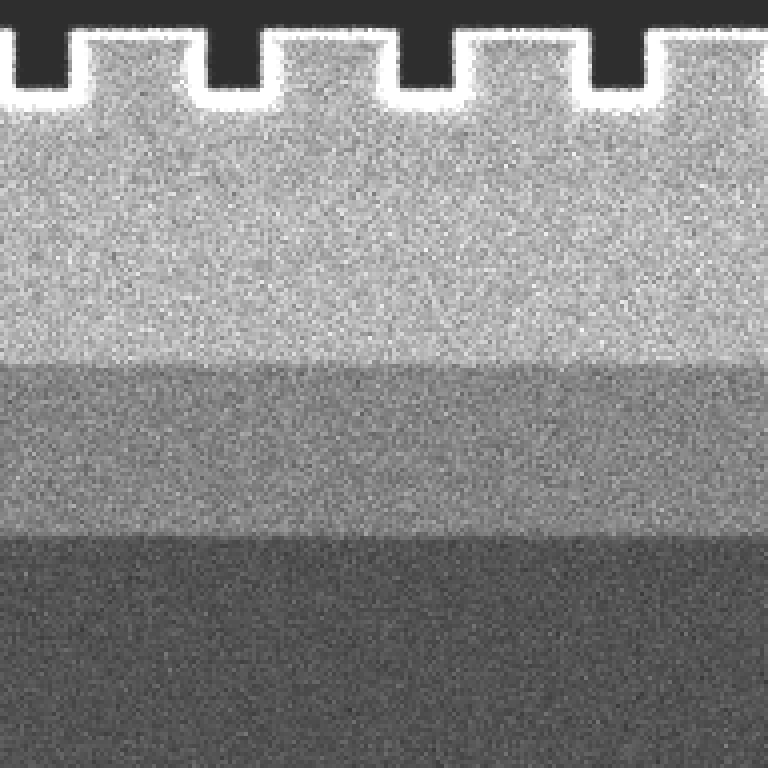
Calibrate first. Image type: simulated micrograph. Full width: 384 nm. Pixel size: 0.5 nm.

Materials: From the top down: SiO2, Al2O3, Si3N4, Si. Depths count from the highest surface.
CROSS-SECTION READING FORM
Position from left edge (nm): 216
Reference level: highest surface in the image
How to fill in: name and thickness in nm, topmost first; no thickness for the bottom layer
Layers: empty 30, SiO2 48, Al2O3 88, Si3N4 86, Si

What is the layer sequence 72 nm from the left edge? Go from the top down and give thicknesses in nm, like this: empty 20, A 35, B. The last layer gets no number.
SiO2 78, Al2O3 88, Si3N4 86, Si